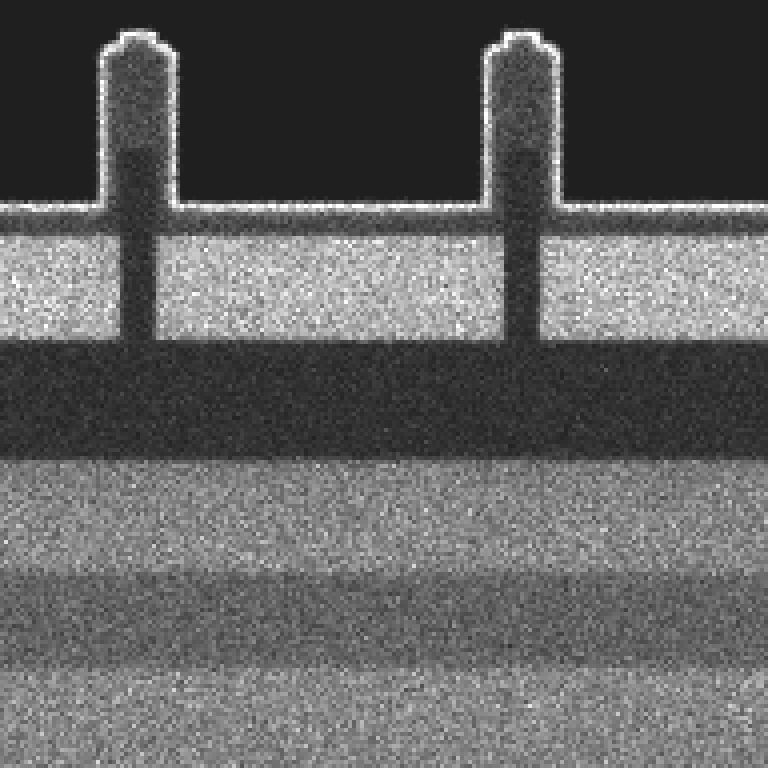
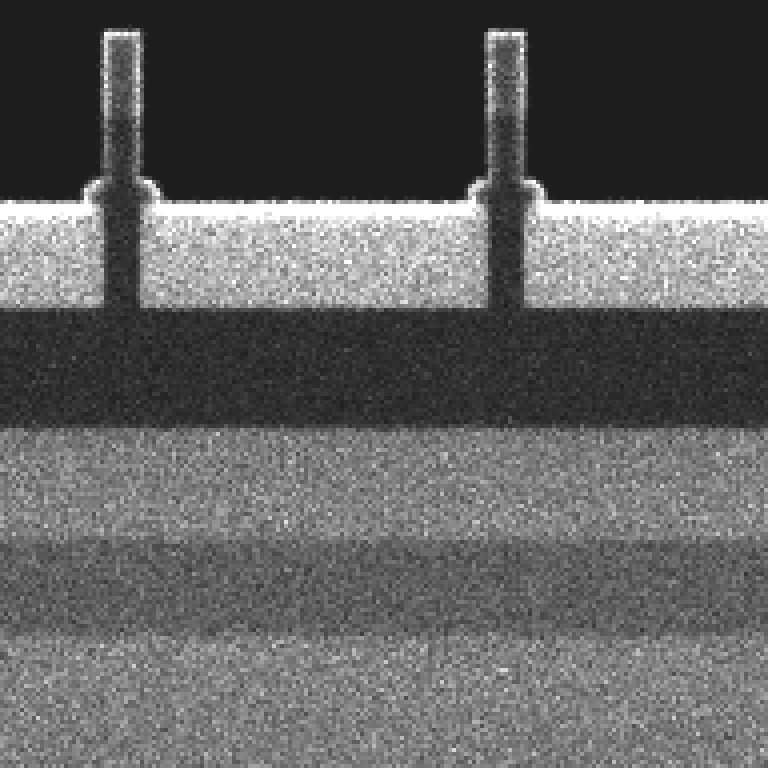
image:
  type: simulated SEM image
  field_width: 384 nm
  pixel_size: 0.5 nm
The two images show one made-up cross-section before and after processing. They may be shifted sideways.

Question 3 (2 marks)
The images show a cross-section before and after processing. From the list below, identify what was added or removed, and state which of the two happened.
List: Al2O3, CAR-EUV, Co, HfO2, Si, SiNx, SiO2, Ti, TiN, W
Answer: SiNx was removed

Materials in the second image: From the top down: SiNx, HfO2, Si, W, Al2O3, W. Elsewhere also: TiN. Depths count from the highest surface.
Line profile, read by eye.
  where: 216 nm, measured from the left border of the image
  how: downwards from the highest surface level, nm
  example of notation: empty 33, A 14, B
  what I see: empty 86, HfO2 52, Si 60, W 56, Al2O3 48, W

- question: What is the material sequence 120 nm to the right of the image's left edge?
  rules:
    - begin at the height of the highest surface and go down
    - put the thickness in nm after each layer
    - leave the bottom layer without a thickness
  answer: empty 86, HfO2 52, Si 60, W 56, Al2O3 48, W